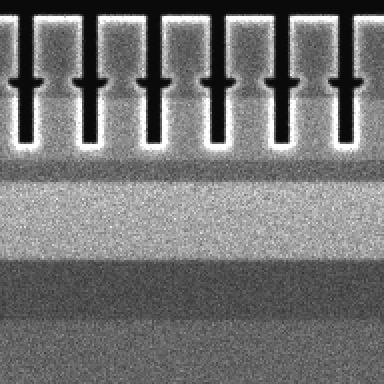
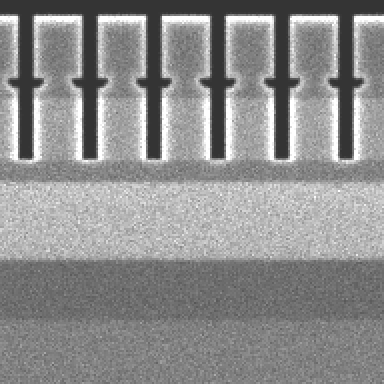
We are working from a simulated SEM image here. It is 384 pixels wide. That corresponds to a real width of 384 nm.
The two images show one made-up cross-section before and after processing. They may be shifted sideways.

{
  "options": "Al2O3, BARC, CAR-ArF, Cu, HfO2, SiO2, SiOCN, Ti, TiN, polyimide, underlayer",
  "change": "removed",
  "material": "SiO2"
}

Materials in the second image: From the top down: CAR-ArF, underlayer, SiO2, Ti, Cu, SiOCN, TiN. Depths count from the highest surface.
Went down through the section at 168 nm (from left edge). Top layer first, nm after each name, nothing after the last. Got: CAR-ArF 62, empty 8, underlayer 12, SiO2 62, Ti 22, Cu 78, SiOCN 60, TiN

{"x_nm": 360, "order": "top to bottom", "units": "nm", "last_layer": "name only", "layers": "CAR-ArF 62, empty 8, underlayer 12, SiO2 62, Ti 22, Cu 78, SiOCN 60, TiN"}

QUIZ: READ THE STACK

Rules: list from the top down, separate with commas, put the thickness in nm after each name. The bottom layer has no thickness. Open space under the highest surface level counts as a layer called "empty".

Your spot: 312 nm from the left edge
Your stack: CAR-ArF 62, underlayer 20, SiO2 62, Ti 22, Cu 78, SiOCN 60, TiN